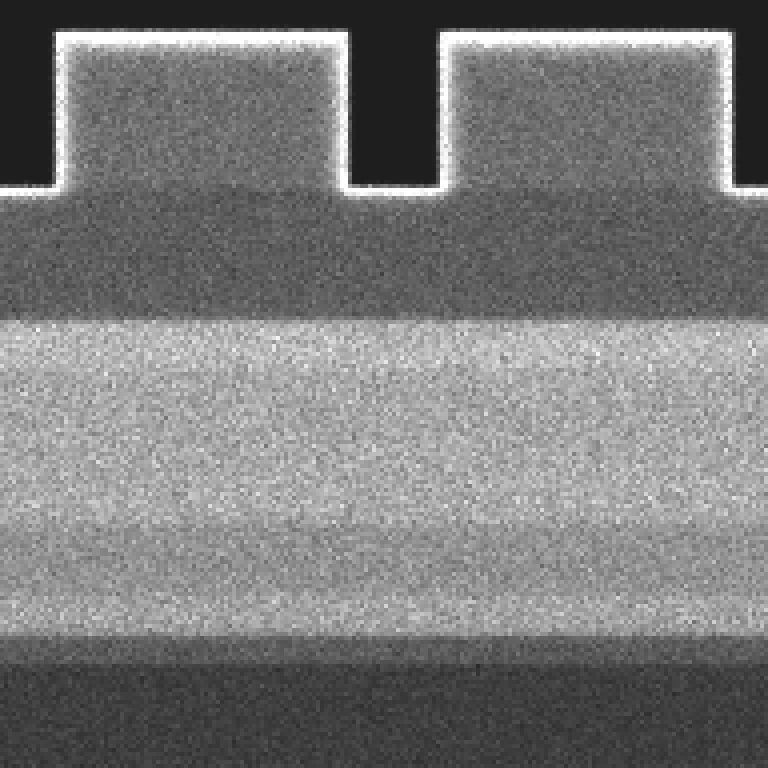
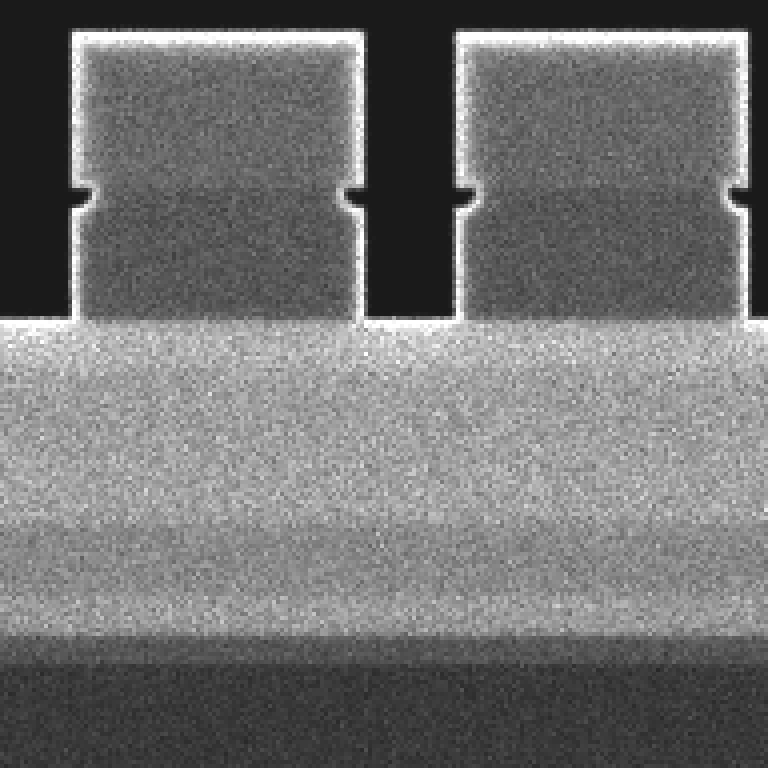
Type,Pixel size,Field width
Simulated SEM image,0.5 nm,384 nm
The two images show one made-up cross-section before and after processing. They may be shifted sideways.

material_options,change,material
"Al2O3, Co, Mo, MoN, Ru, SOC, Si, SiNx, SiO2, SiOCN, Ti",removed,SiNx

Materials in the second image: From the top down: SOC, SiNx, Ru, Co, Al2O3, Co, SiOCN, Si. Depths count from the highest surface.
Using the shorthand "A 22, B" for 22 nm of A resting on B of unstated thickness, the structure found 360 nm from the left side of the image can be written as SOC 78, SiNx 66, Ru 24, Co 78, Al2O3 36, Co 20, SiOCN 14, Si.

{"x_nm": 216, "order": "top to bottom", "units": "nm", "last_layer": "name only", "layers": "empty 144, Ru 24, Co 78, Al2O3 36, Co 20, SiOCN 14, Si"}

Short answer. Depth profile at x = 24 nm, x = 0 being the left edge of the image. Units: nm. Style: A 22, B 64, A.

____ empty 144, Ru 24, Co 78, Al2O3 36, Co 20, SiOCN 14, Si